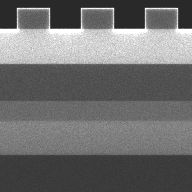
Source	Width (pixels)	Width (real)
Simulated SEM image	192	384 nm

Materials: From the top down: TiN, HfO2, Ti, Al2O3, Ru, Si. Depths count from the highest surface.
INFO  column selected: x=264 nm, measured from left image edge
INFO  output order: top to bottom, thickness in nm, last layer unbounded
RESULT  empty 42, HfO2 70, Ti 74, Al2O3 40, Ru 68, Si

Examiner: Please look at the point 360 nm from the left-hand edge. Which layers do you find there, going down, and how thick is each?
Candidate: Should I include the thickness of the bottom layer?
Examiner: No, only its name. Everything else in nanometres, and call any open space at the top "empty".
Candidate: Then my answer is empty 42, HfO2 70, Ti 74, Al2O3 40, Ru 68, Si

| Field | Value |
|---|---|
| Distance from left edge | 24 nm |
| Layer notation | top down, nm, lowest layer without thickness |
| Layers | empty 42, HfO2 70, Ti 74, Al2O3 40, Ru 68, Si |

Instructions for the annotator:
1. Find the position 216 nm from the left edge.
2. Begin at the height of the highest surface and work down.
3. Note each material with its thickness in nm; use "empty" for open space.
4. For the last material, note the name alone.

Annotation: TiN 42, HfO2 70, Ti 74, Al2O3 40, Ru 68, Si